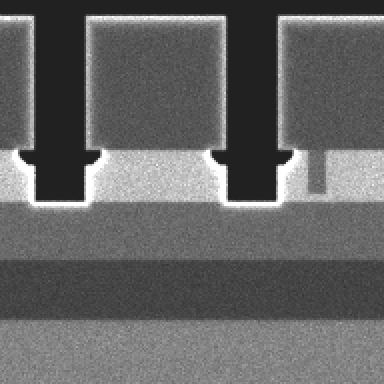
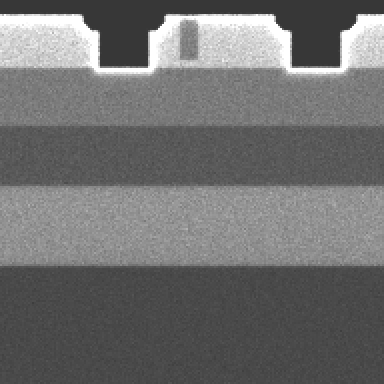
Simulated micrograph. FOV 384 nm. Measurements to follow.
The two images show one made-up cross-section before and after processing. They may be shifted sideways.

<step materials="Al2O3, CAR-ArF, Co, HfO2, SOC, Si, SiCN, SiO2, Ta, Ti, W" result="removed SOC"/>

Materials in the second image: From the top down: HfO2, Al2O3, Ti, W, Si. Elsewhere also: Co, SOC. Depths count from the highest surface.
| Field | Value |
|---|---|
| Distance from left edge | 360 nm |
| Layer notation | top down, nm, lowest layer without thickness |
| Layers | HfO2 52, Al2O3 58, Ti 60, W 80, Si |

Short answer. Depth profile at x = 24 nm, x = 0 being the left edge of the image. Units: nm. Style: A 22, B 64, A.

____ HfO2 52, Al2O3 58, Ti 60, W 80, Si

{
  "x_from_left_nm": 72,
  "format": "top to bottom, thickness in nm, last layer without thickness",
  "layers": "HfO2 52, Al2O3 58, Ti 60, W 80, Si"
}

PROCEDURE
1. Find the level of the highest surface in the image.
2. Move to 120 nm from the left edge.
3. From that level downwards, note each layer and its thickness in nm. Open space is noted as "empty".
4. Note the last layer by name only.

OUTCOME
empty 52, Al2O3 58, Ti 60, W 80, Si